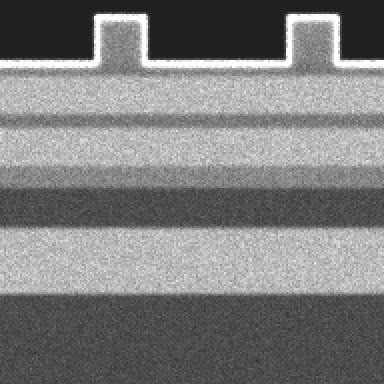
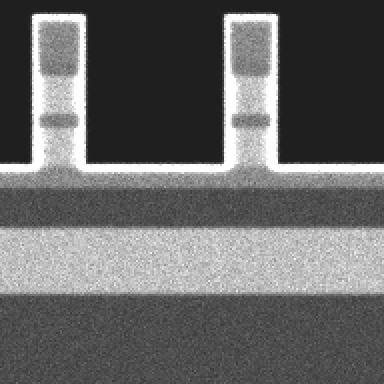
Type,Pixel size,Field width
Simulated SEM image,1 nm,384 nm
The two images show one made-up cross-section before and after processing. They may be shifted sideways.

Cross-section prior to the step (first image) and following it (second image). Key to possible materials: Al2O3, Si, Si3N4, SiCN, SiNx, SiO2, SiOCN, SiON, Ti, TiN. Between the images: SiNx and SiO2 was removed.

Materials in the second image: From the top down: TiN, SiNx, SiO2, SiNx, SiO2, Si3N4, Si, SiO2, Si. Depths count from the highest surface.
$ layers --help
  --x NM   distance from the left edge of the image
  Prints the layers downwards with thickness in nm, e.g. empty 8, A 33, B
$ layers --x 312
empty 150, Si3N4 22, Si 40, SiO2 66, Si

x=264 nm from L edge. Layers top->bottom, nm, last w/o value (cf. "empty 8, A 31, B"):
TiN 46, SiNx 14, SiO2 38, SiNx 14, SiO2 38, Si3N4 22, Si 40, SiO2 66, Si